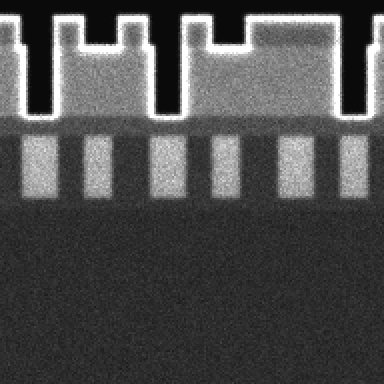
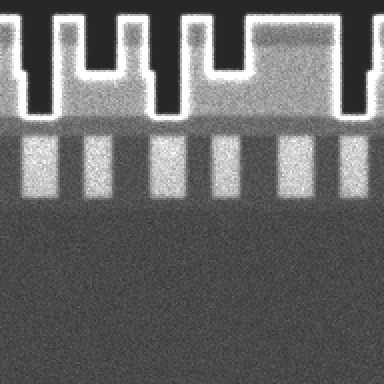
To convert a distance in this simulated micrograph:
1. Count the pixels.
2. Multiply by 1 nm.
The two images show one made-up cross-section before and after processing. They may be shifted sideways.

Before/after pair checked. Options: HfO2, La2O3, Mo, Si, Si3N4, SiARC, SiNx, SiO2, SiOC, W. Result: removed SiO2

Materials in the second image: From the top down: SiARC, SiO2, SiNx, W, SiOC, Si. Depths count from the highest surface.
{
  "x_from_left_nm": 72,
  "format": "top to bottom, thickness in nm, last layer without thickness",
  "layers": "SiARC 30, SiO2 70, SiNx 20, SiOC 74, Si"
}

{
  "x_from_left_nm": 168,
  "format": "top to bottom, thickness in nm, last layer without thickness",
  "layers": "empty 100, SiNx 20, W 62, SiOC 12, Si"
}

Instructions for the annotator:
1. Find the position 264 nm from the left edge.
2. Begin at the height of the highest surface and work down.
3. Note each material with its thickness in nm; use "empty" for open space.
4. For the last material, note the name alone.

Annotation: SiARC 30, SiO2 70, SiNx 20, SiOC 74, Si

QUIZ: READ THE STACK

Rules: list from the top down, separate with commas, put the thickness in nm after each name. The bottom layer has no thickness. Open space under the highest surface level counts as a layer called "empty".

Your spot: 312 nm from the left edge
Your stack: SiARC 30, SiO2 70, SiNx 20, W 62, SiOC 12, Si